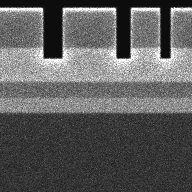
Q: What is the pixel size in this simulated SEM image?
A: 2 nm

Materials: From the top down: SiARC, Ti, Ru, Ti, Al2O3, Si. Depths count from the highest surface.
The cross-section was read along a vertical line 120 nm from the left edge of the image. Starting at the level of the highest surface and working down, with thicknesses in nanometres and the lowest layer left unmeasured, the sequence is empty 102, Ru 46, Ti 32, Al2O3 30, Si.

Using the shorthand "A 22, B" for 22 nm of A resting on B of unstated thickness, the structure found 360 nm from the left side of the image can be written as SiARC 14, Ti 66, Ru 68, Ti 32, Al2O3 30, Si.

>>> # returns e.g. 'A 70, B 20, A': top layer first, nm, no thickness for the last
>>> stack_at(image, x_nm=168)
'SiARC 14, Ti 66, Ru 68, Ti 32, Al2O3 30, Si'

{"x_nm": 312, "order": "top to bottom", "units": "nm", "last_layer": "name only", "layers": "SiARC 14, Ti 66, Ru 68, Ti 32, Al2O3 30, Si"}